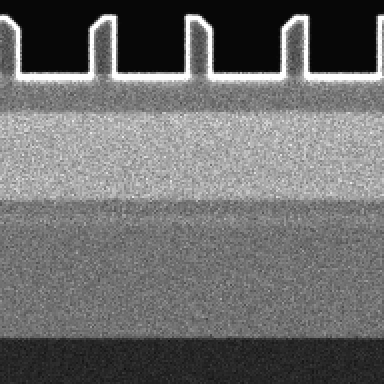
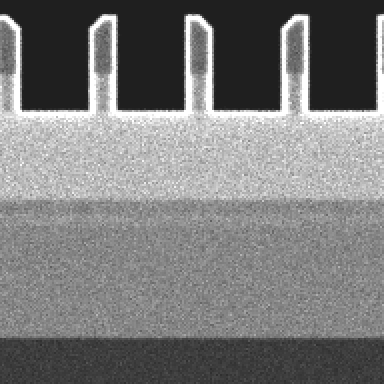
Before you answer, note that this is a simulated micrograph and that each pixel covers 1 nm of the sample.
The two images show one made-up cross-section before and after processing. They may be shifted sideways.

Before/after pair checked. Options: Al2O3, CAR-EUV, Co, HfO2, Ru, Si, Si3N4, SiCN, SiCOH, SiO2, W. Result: removed Al2O3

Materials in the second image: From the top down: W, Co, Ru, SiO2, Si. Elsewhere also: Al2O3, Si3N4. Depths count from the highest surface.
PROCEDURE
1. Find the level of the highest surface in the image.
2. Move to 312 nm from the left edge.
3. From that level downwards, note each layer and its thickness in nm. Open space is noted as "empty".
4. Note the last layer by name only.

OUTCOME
empty 96, W 88, Co 14, Ru 12, SiO2 112, Si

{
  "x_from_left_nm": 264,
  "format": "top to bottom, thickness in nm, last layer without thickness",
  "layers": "empty 96, W 88, Co 14, Ru 12, SiO2 112, Si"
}